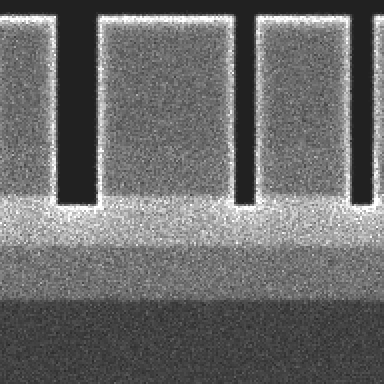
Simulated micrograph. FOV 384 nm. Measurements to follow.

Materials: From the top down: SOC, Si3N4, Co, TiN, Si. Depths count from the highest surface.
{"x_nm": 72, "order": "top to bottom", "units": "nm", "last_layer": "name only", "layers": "empty 190, Co 40, TiN 54, Si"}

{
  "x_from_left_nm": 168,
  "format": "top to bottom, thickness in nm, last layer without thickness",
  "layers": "SOC 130, Si3N4 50, Co 50, TiN 54, Si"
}